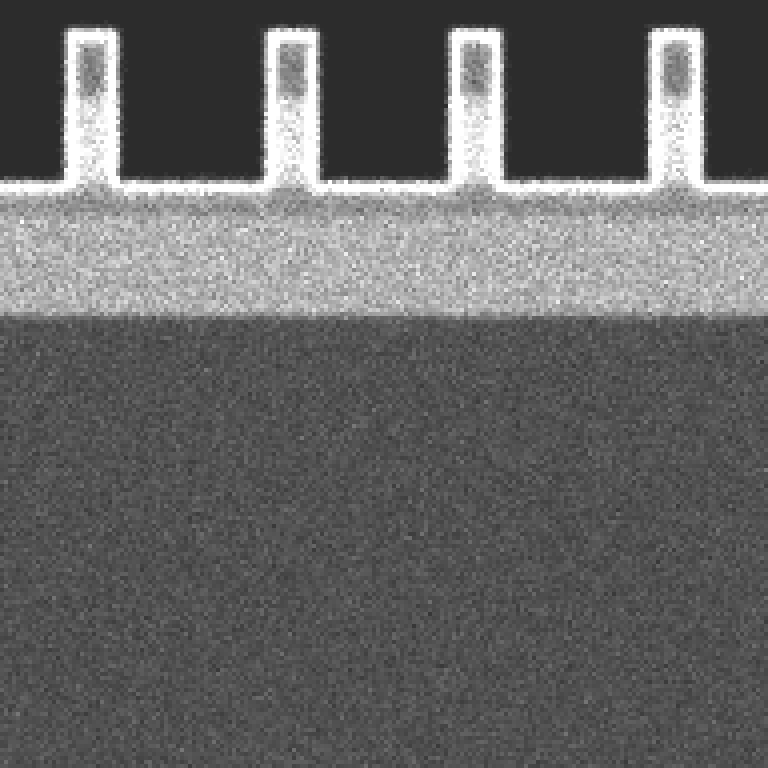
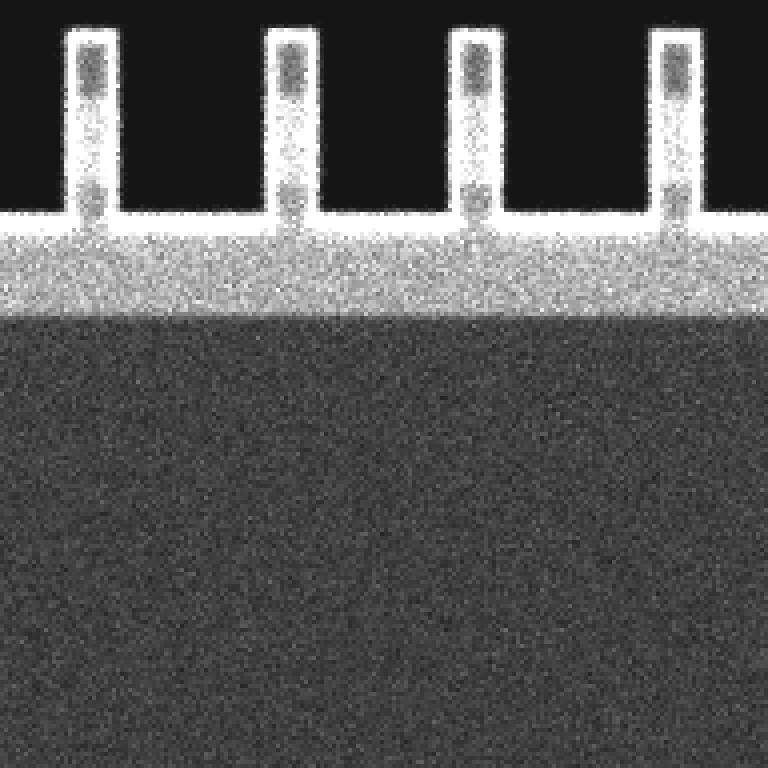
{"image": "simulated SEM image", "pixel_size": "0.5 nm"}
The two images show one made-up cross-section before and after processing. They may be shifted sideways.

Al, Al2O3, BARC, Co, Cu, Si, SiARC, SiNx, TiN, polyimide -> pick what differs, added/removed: TiN removed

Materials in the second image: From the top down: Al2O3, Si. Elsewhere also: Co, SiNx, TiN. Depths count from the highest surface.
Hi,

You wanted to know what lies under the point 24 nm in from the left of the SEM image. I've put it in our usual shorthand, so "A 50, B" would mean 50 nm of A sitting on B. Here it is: empty 92, Al2O3 50, Si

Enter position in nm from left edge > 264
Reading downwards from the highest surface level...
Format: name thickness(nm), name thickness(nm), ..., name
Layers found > empty 92, Al2O3 50, Si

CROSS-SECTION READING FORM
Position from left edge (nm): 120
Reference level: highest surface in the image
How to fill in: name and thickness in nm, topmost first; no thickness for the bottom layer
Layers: empty 92, Al2O3 50, Si